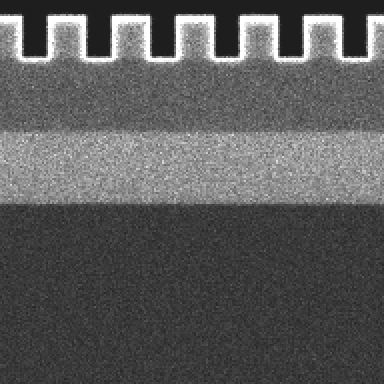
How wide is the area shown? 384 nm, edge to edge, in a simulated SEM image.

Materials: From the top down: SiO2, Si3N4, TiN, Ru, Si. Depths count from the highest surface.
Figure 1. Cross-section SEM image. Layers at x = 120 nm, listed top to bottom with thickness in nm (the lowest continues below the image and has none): SiO2 42, Si3N4 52, TiN 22, Ru 72, Si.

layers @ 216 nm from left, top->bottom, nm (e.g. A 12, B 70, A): empty 42, Si3N4 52, TiN 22, Ru 72, Si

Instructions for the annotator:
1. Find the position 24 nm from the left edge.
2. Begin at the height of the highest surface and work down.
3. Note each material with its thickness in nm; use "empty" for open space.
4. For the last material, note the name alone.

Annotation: empty 42, Si3N4 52, TiN 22, Ru 72, Si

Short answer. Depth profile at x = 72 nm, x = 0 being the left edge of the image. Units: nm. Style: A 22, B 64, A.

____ SiO2 42, Si3N4 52, TiN 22, Ru 72, Si